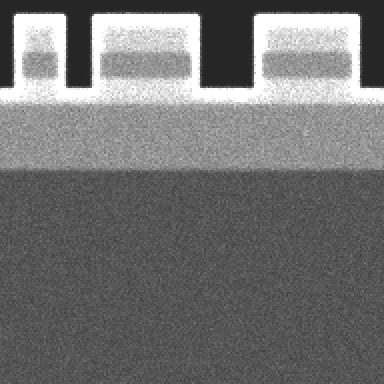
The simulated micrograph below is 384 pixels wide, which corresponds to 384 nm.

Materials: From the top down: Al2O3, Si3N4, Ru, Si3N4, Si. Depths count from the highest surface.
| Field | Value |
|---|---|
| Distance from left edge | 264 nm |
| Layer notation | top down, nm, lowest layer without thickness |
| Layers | Al2O3 36, Si3N4 26, Ru 26, Si3N4 66, Si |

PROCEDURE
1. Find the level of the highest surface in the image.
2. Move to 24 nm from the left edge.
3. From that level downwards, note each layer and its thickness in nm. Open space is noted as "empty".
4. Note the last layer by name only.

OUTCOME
Al2O3 36, Si3N4 26, Ru 26, Si3N4 66, Si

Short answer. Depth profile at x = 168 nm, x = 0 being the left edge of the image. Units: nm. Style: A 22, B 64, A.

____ Al2O3 36, Si3N4 26, Ru 26, Si3N4 66, Si